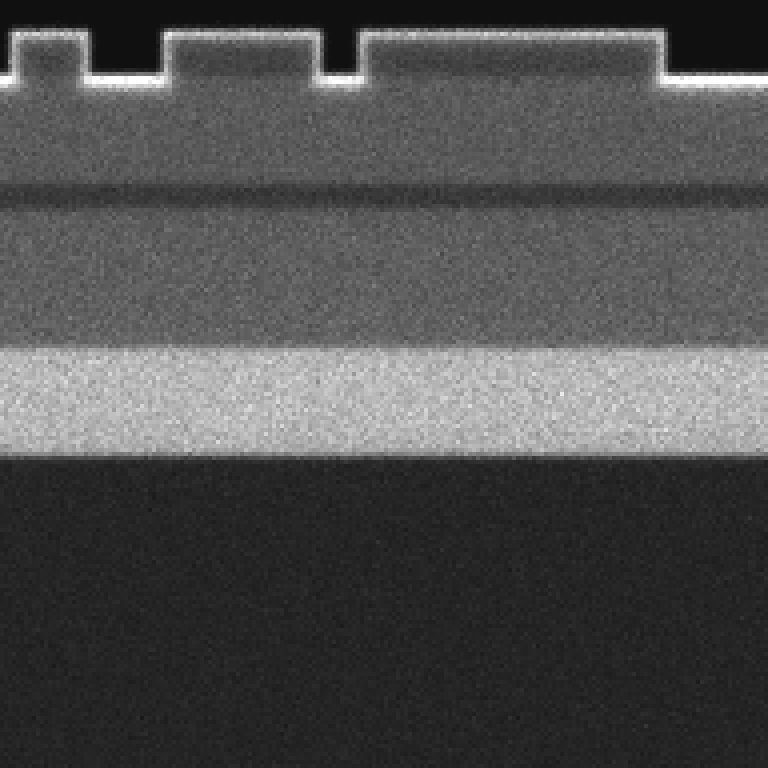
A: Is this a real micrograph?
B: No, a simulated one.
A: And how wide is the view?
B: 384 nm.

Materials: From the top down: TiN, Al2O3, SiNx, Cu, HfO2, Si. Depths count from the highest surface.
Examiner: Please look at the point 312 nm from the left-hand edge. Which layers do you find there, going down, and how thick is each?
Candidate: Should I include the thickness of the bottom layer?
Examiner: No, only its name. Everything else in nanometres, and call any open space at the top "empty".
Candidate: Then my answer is TiN 22, Al2O3 54, SiNx 12, Cu 70, HfO2 54, Si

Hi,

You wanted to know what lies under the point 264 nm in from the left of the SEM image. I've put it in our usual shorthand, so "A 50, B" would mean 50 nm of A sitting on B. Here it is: TiN 22, Al2O3 54, SiNx 12, Cu 70, HfO2 54, Si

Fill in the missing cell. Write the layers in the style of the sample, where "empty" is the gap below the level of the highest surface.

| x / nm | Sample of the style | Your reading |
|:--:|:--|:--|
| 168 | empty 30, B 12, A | empty 22, Al2O3 54, SiNx 12, Cu 70, HfO2 54, Si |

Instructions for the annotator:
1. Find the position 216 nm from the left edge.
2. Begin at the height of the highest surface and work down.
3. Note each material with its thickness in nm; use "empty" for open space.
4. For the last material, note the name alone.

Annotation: TiN 22, Al2O3 54, SiNx 12, Cu 70, HfO2 54, Si